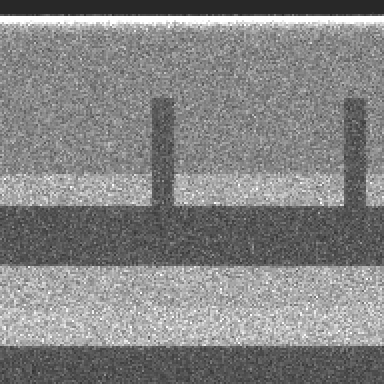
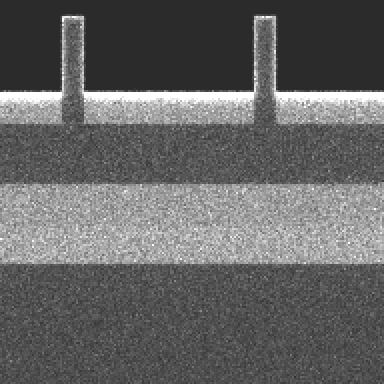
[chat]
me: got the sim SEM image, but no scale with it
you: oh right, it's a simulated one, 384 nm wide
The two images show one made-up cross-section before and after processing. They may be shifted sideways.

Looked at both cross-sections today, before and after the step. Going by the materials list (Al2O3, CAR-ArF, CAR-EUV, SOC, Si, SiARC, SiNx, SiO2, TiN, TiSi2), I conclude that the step removed SOC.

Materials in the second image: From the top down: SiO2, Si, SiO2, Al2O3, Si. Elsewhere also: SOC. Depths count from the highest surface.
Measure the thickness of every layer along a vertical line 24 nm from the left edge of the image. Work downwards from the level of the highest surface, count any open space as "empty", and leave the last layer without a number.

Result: empty 76, SiO2 32, Si 60, SiO2 42, Al2O3 38, Si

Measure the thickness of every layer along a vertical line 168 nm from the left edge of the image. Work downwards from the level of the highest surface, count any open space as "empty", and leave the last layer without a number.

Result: empty 76, SiO2 32, Si 60, SiO2 42, Al2O3 38, Si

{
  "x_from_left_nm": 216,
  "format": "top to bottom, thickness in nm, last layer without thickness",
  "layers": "empty 76, SiO2 32, Si 60, SiO2 42, Al2O3 38, Si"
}